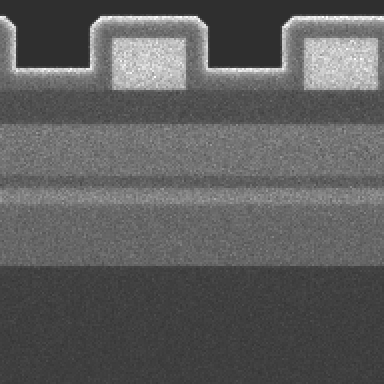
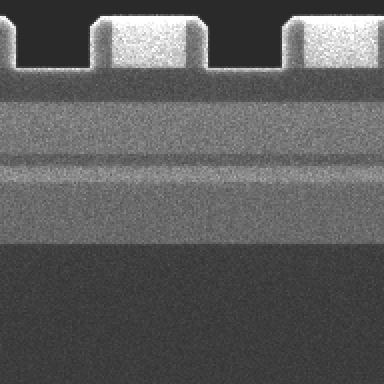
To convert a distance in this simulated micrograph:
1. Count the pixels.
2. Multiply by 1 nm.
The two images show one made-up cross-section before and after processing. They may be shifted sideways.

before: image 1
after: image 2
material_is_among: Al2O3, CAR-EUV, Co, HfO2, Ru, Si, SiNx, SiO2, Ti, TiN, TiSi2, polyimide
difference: SiO2, removed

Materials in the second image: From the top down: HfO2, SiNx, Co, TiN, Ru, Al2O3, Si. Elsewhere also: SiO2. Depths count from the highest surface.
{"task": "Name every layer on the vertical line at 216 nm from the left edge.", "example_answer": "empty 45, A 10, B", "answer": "empty 52, SiNx 34, Co 52, TiN 12, Ru 16, Al2O3 62, Si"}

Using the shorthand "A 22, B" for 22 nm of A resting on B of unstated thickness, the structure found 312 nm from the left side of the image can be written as HfO2 52, SiNx 34, Co 52, TiN 12, Ru 16, Al2O3 62, Si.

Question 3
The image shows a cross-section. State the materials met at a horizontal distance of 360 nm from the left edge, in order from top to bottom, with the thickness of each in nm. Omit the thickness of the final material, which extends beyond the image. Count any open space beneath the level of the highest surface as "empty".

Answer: HfO2 52, SiNx 34, Co 52, TiN 12, Ru 16, Al2O3 62, Si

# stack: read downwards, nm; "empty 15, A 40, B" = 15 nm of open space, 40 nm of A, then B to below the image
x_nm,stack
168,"HfO2 52, SiNx 34, Co 52, TiN 12, Ru 16, Al2O3 62, Si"